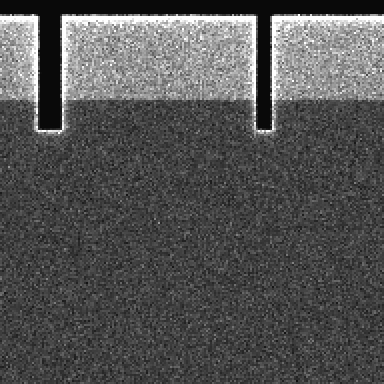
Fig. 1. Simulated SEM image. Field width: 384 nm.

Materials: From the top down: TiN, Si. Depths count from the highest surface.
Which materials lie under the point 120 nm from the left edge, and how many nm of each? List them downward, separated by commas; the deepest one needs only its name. TiN 84, Si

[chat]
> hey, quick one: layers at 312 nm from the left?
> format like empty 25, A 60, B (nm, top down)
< TiN 84, Si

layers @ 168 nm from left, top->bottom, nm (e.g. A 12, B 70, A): TiN 84, Si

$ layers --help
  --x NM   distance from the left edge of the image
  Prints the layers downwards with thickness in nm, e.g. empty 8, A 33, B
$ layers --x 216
TiN 84, Si